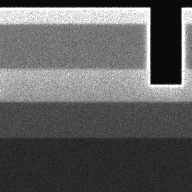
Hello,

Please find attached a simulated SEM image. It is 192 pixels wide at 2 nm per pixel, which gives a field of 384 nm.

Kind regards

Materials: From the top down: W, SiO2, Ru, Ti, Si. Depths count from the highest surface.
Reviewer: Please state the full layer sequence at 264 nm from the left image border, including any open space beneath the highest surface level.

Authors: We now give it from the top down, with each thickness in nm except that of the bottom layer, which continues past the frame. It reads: W 32, SiO2 90, Ru 66, Ti 72, Si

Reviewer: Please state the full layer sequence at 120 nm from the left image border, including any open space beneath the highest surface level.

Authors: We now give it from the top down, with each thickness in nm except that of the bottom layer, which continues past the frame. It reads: W 32, SiO2 90, Ru 66, Ti 72, Si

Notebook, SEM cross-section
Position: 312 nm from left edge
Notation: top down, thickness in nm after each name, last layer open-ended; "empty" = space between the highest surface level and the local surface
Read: empty 154, Ru 34, Ti 72, Si